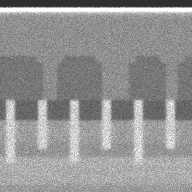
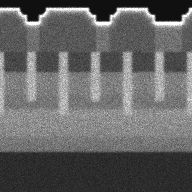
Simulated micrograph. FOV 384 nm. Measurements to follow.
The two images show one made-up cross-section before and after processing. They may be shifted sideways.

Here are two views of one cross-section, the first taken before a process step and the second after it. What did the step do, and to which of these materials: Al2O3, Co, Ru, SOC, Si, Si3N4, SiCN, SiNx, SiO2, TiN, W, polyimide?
It removed SiO2.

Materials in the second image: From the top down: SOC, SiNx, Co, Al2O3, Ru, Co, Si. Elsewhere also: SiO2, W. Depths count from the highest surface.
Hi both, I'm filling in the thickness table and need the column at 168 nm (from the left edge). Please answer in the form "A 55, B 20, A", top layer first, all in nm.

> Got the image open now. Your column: SOC 88, SiNx 40, Co 46, Al2O3 28, Ru 56, Co 30, Si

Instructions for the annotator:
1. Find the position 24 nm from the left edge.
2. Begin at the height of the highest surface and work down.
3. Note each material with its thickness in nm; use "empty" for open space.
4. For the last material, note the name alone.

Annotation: SOC 88, SiNx 40, Co 46, Al2O3 28, Ru 56, Co 30, Si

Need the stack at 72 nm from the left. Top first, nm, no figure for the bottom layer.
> empty 28, SiO2 60, SiNx 40, Co 46, Al2O3 28, Ru 56, Co 30, Si